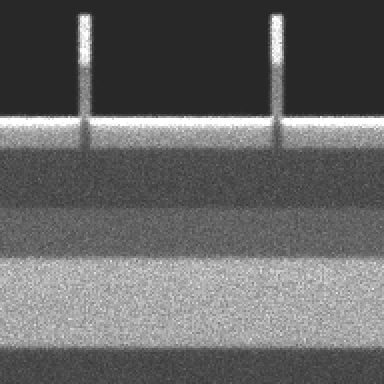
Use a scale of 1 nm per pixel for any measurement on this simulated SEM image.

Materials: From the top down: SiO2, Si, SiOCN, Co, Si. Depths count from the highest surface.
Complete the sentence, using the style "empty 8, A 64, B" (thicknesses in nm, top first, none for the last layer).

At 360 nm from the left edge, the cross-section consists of empty 102, SiO2 30, Si 60, SiOCN 50, Co 90, Si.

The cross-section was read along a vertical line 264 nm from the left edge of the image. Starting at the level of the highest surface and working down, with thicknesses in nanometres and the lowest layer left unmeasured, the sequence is empty 102, SiO2 30, Si 60, SiOCN 50, Co 90, Si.